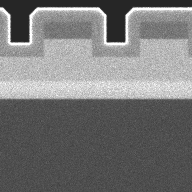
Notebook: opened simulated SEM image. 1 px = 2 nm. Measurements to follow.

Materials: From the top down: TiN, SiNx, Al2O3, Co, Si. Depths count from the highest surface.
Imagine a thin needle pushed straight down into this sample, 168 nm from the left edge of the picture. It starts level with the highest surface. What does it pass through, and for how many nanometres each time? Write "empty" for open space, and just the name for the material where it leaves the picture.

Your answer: TiN 28, SiNx 34, Al2O3 84, Co 36, Si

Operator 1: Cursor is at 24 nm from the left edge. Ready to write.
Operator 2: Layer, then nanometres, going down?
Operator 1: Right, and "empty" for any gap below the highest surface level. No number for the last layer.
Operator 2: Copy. empty 70, TiN 28, Al2O3 48, Co 36, Si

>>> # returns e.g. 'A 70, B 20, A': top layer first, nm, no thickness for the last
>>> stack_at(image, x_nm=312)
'TiN 28, SiNx 34, Al2O3 84, Co 36, Si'